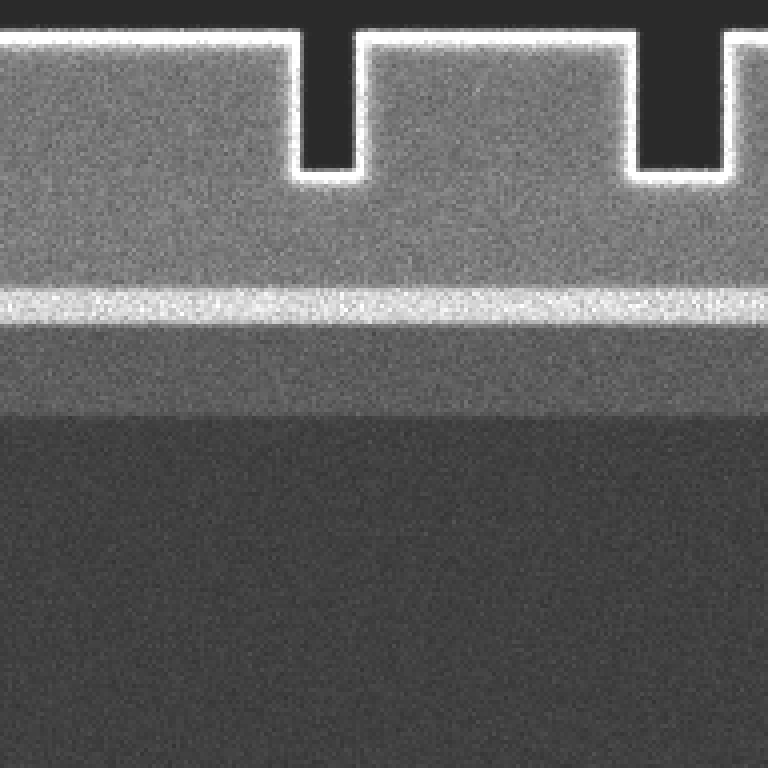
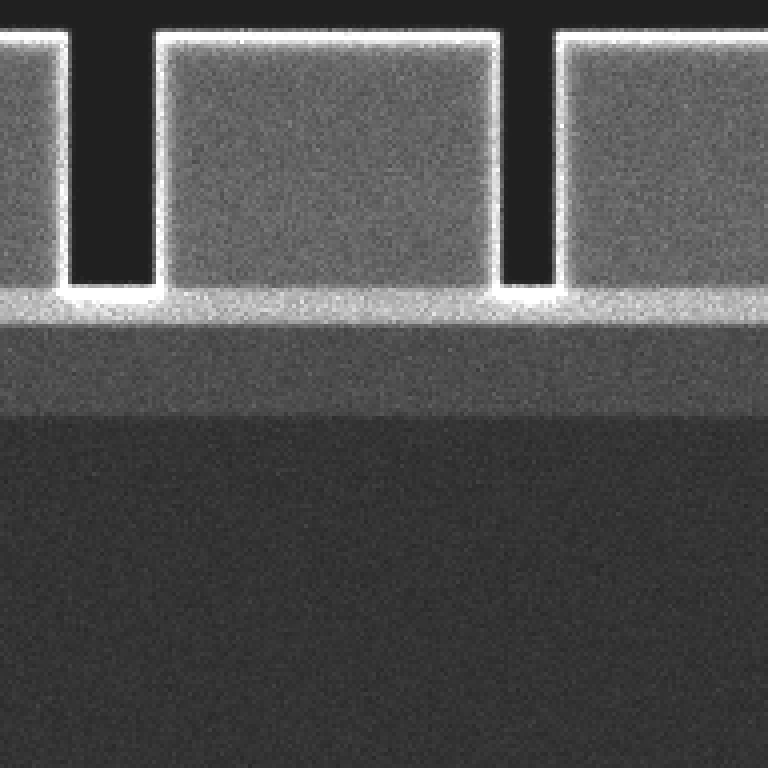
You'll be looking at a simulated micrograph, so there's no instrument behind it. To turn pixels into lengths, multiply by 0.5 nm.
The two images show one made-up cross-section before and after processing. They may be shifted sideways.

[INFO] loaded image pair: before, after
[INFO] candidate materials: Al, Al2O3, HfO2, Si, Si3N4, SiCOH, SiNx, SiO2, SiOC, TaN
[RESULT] removed Al2O3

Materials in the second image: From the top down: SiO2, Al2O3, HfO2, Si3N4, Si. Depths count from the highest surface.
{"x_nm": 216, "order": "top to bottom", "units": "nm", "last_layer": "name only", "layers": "SiO2 70, Al2O3 58, HfO2 18, Si3N4 46, Si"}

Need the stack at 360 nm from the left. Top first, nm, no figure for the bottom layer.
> SiO2 70, Al2O3 58, HfO2 18, Si3N4 46, Si